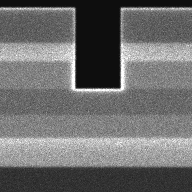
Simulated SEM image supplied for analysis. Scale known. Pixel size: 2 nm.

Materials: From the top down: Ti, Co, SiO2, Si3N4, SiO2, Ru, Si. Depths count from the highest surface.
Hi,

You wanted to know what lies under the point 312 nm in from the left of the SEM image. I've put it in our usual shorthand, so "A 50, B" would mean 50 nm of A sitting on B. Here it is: Ti 70, Co 36, SiO2 56, Si3N4 52, SiO2 46, Ru 58, Si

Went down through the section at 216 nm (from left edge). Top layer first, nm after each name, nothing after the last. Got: empty 162, Si3N4 52, SiO2 46, Ru 58, Si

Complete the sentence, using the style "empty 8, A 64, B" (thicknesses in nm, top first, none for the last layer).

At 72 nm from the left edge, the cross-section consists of Ti 70, Co 36, SiO2 56, Si3N4 52, SiO2 46, Ru 58, Si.